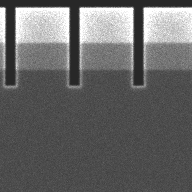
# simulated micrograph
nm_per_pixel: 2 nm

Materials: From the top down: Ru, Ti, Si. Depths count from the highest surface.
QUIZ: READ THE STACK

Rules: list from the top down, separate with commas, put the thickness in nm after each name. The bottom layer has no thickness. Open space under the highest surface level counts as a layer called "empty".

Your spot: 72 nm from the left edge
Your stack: Ru 70, Ti 54, Si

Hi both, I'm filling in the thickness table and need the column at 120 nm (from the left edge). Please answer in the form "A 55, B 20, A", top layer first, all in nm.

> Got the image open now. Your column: Ru 70, Ti 54, Si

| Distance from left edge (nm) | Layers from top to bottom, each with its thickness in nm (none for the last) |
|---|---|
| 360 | Ru 70, Ti 54, Si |